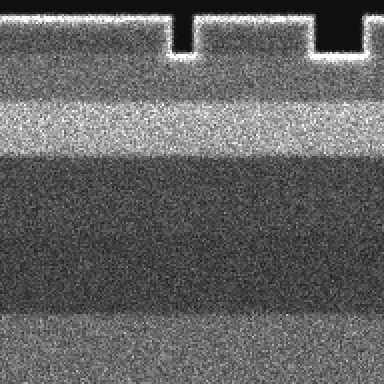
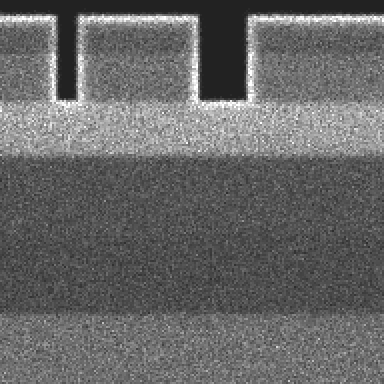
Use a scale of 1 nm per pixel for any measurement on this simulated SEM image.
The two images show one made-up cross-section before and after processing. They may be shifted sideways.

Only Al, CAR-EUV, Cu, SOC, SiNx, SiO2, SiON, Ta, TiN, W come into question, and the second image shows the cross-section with SiO2 removed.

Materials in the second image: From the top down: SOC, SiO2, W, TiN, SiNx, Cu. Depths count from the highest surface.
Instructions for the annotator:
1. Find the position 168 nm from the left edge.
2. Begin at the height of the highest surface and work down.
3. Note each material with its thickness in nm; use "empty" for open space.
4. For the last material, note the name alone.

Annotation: SOC 38, SiO2 48, W 54, TiN 78, SiNx 80, Cu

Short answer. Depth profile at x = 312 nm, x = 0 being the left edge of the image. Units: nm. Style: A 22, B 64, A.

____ SOC 38, SiO2 48, W 54, TiN 78, SiNx 80, Cu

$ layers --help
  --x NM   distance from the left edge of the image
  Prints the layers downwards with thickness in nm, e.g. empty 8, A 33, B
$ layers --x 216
empty 86, W 54, TiN 78, SiNx 80, Cu